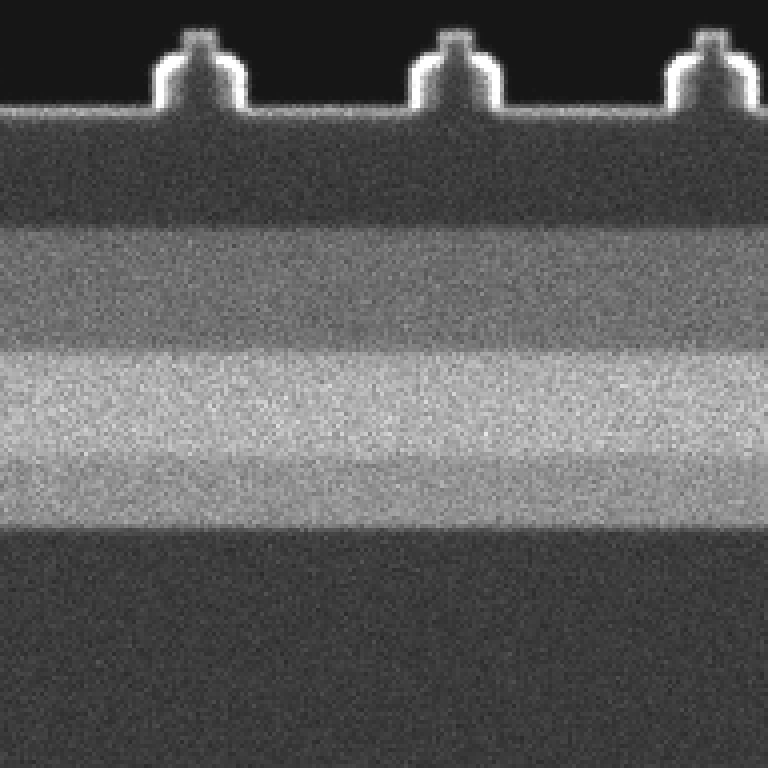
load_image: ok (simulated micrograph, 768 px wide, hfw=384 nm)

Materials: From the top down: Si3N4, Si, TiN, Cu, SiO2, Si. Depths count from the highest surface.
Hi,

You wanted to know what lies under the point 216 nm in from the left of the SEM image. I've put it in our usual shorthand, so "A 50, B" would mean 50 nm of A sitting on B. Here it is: empty 12, Si3N4 26, Si 60, TiN 62, Cu 52, SiO2 36, Si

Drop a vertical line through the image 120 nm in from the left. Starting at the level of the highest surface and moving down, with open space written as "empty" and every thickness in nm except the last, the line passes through empty 18, Si3N4 20, Si 60, TiN 62, Cu 52, SiO2 36, Si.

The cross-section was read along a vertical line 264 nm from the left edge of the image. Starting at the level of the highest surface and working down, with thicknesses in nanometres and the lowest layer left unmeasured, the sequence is empty 38, Si 60, TiN 62, Cu 52, SiO2 36, Si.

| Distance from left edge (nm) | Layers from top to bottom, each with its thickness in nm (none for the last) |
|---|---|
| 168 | empty 38, Si 60, TiN 62, Cu 52, SiO2 36, Si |